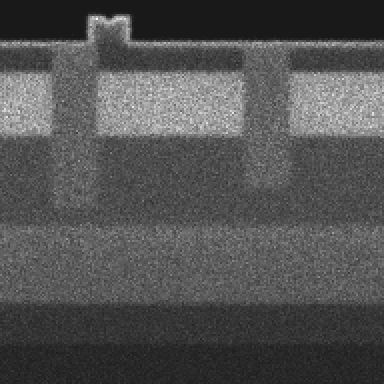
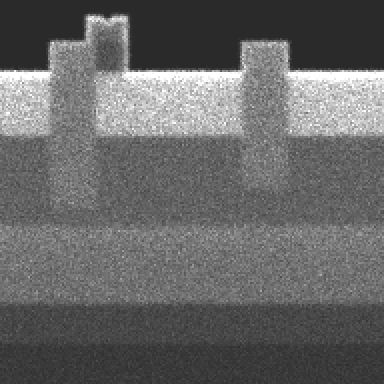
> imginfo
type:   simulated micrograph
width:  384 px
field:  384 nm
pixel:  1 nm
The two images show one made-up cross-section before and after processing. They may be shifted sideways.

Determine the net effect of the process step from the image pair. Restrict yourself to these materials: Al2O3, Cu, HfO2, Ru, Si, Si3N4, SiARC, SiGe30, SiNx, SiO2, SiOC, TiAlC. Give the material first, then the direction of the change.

Si3N4: removed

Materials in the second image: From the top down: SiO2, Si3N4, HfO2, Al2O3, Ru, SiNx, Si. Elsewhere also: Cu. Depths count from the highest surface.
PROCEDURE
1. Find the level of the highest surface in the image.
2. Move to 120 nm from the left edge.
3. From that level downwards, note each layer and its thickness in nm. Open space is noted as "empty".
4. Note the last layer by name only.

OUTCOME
SiO2 26, Si3N4 30, HfO2 64, Al2O3 90, Ru 78, SiNx 40, Si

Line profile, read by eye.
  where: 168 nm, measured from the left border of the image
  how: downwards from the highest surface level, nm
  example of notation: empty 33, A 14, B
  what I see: empty 56, HfO2 64, Al2O3 90, Ru 78, SiNx 40, Si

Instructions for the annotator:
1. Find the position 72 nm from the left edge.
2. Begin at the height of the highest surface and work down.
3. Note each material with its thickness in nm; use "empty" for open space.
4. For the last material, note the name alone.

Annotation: empty 26, Cu 166, Al2O3 18, Ru 78, SiNx 40, Si